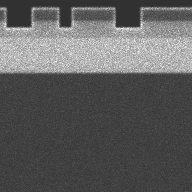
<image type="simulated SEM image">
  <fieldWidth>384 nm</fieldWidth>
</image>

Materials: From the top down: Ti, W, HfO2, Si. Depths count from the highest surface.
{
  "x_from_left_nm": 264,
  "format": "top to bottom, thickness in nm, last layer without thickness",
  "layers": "empty 40, W 20, HfO2 70, Si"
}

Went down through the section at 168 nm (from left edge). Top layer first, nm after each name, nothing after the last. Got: Ti 26, W 34, HfO2 70, Si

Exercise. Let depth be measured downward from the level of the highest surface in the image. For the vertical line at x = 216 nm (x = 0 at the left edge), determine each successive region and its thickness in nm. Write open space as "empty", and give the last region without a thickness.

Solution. Ti 26, W 34, HfO2 70, Si